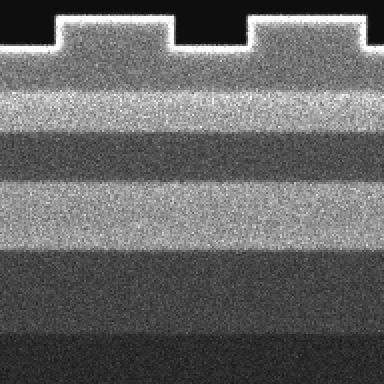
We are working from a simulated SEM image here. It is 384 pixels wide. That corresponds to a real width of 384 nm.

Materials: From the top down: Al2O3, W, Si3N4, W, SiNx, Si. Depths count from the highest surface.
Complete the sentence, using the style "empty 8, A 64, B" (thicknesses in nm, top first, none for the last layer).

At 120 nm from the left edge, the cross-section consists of Al2O3 76, W 40, Si3N4 50, W 68, SiNx 84, Si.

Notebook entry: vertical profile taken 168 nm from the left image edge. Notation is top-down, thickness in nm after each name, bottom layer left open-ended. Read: Al2O3 76, W 40, Si3N4 50, W 68, SiNx 84, Si